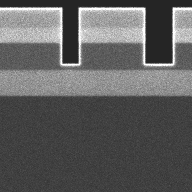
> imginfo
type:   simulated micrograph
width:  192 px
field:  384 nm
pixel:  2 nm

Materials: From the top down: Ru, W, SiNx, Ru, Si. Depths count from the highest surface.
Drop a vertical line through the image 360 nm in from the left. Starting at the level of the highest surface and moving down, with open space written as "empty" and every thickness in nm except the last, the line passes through Ru 40, W 30, SiNx 54, Ru 52, Si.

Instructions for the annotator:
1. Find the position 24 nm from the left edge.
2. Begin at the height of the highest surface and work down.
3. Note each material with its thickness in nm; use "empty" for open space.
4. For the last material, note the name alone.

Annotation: Ru 40, W 30, SiNx 54, Ru 52, Si